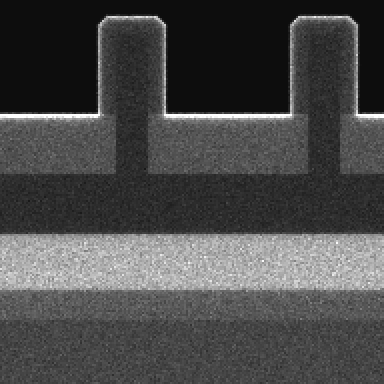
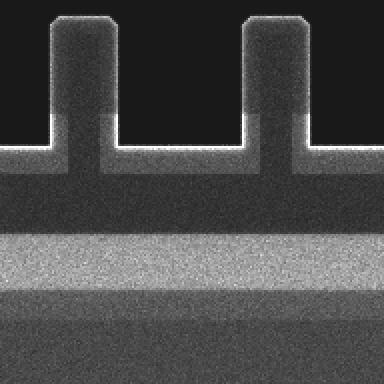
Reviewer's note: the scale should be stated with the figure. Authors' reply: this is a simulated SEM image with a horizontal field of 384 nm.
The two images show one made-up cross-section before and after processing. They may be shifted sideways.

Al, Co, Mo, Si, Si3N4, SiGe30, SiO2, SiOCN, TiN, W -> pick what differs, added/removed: Si3N4 removed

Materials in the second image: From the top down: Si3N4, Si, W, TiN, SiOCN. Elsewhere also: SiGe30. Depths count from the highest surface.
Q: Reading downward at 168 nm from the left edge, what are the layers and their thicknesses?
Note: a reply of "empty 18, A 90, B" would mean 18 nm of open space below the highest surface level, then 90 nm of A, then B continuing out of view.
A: empty 130, Si3N4 28, Si 60, W 56, TiN 30, SiOCN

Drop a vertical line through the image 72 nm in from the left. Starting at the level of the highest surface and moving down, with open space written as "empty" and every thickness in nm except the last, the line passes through SiGe30 18, Si 200, W 56, TiN 30, SiOCN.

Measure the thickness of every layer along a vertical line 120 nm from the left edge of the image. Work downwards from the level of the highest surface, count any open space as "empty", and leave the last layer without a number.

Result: empty 130, Si3N4 28, Si 60, W 56, TiN 30, SiOCN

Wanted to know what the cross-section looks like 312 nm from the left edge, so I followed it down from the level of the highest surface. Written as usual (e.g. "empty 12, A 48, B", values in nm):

empty 130, Si3N4 28, Si 60, W 56, TiN 30, SiOCN